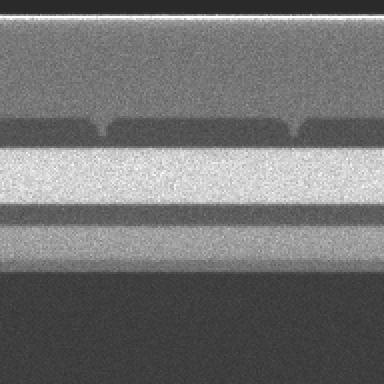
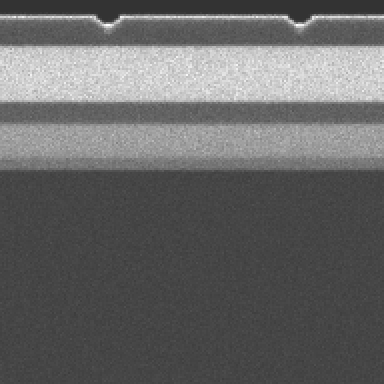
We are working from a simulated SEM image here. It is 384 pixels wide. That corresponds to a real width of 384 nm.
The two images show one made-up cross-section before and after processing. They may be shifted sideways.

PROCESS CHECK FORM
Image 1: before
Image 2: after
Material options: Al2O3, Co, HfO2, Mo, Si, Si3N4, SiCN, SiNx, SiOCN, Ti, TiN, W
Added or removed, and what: removed, Co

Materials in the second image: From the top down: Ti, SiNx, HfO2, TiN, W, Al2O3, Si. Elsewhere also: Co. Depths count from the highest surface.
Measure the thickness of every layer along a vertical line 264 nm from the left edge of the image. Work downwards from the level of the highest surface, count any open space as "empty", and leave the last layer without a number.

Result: Ti 12, SiNx 18, HfO2 56, TiN 22, W 34, Al2O3 12, Si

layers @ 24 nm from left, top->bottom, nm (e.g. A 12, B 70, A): Ti 12, SiNx 18, HfO2 56, TiN 22, W 34, Al2O3 12, Si